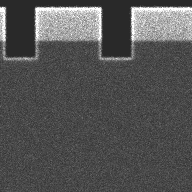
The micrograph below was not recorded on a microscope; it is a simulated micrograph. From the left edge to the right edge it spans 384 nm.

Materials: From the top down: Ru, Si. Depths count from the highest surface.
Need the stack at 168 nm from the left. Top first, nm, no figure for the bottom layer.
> Ru 66, Si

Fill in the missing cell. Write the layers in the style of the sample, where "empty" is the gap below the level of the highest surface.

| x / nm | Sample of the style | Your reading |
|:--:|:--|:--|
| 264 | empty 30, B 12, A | Ru 66, Si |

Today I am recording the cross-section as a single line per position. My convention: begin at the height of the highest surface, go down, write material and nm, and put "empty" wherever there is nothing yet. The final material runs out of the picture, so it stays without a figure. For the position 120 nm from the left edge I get Ru 66, Si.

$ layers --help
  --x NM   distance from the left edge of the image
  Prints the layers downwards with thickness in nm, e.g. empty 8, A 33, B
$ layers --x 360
Ru 66, Si